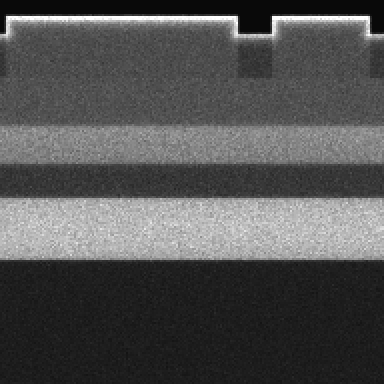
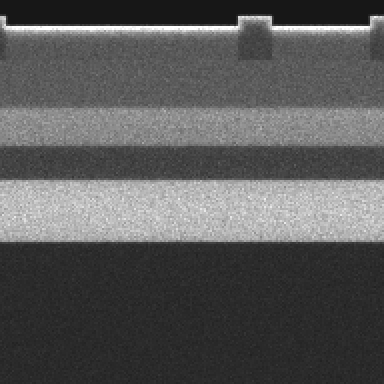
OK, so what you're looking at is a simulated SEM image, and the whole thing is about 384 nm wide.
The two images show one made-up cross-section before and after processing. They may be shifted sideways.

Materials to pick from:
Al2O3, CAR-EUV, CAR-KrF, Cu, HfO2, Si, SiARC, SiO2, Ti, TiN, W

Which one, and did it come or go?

SiO2 - removed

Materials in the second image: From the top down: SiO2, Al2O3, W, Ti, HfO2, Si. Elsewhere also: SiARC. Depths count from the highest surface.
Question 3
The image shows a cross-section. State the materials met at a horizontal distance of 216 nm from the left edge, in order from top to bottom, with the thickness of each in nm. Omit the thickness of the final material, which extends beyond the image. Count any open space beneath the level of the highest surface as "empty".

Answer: empty 10, SiO2 34, Al2O3 48, W 38, Ti 34, HfO2 62, Si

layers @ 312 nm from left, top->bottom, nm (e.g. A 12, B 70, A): empty 10, SiO2 34, Al2O3 48, W 38, Ti 34, HfO2 62, Si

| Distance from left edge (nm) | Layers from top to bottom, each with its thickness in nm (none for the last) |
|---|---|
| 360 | empty 10, SiO2 34, Al2O3 48, W 38, Ti 34, HfO2 62, Si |